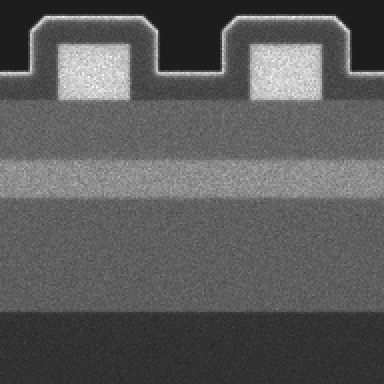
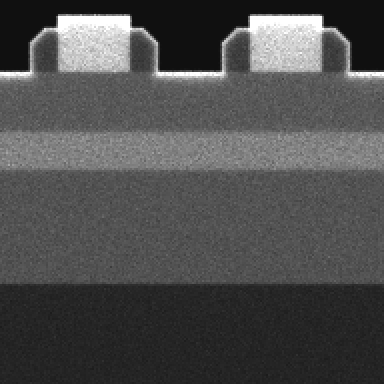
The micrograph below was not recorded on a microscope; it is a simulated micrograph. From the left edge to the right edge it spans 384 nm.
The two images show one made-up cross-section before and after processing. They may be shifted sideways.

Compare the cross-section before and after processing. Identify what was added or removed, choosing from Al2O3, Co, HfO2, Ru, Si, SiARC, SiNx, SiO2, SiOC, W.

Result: SiNx removed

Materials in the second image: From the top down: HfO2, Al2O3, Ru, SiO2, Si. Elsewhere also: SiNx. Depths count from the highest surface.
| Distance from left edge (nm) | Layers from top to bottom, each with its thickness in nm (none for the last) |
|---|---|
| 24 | empty 56, Al2O3 60, Ru 38, SiO2 114, Si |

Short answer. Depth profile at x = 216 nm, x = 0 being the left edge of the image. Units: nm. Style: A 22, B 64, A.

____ empty 56, Al2O3 60, Ru 38, SiO2 114, Si